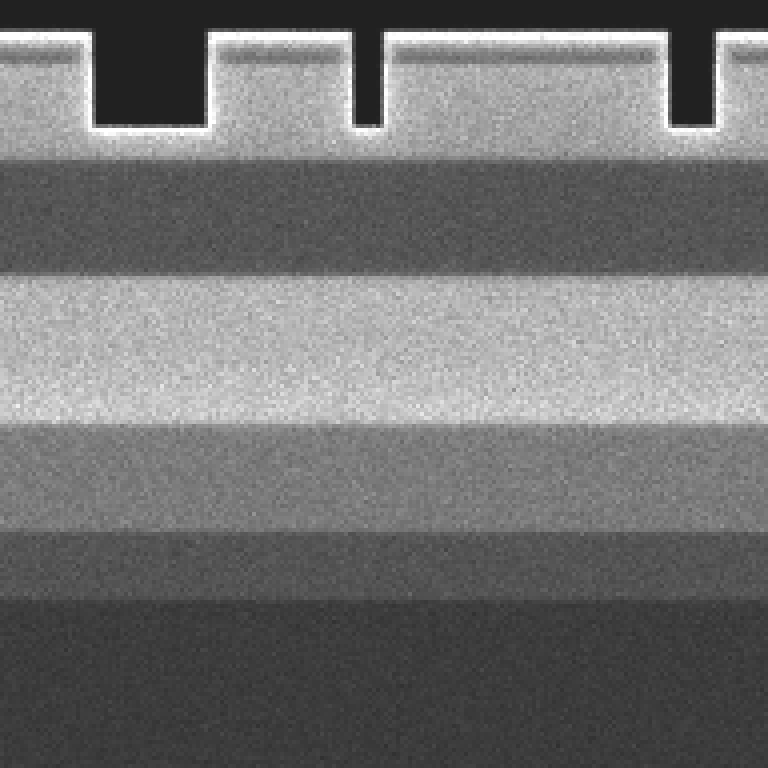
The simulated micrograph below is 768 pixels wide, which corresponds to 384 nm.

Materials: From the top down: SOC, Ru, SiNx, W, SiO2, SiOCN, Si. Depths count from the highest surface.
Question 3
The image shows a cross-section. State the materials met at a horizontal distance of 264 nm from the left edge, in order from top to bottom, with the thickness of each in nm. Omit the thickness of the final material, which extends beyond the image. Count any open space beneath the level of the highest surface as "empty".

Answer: SOC 16, Ru 48, SiNx 58, W 74, SiO2 54, SiOCN 34, Si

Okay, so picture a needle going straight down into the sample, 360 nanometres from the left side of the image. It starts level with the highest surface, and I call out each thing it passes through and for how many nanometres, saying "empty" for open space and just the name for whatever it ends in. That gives SOC 16, Ru 48, SiNx 58, W 74, SiO2 54, SiOCN 34, Si